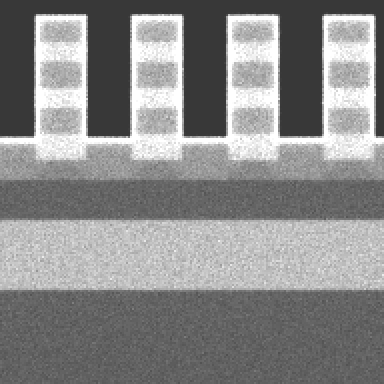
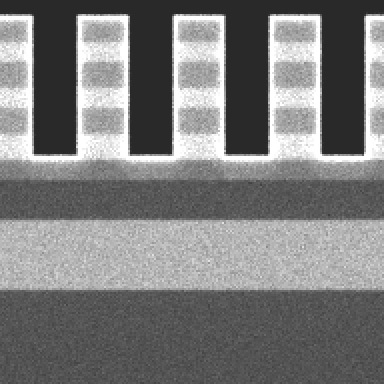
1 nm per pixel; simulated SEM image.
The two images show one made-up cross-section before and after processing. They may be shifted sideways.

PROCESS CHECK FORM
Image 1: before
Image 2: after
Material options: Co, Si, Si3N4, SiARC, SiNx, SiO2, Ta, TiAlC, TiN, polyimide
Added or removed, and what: removed, Si3N4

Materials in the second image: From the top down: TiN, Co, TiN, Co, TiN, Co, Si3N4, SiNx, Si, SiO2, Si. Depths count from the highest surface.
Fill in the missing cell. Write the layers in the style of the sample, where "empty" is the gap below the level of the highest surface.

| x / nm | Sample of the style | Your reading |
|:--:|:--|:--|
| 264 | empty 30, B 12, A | empty 140, Si3N4 24, Si 40, SiO2 70, Si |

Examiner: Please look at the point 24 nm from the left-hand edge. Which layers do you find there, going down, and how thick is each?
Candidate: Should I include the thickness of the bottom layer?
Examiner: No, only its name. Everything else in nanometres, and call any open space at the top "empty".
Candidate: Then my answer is TiN 26, Co 20, TiN 26, Co 20, TiN 26, Co 26, Si3N4 10, SiNx 10, Si 40, SiO2 70, Si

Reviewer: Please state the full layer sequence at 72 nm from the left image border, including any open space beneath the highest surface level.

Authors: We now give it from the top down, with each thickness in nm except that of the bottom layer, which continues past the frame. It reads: empty 140, Si3N4 24, Si 40, SiO2 70, Si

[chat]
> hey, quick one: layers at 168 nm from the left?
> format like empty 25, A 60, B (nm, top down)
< empty 140, Si3N4 24, Si 40, SiO2 70, Si